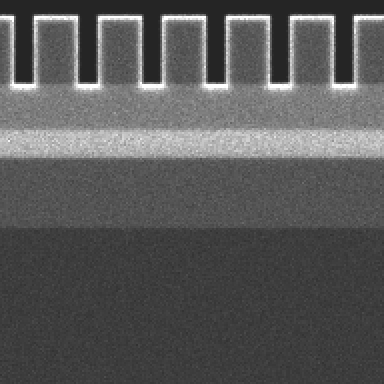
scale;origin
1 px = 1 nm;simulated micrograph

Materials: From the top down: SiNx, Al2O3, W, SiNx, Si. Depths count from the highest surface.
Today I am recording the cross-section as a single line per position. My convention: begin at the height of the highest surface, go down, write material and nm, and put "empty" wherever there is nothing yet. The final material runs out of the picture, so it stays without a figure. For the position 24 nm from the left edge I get empty 68, Al2O3 46, W 28, SiNx 70, Si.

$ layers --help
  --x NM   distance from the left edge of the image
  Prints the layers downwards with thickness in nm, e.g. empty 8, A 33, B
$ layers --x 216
empty 68, Al2O3 46, W 28, SiNx 70, Si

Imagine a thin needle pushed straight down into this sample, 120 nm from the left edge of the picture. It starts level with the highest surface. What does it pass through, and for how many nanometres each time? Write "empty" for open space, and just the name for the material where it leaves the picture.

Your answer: SiNx 68, Al2O3 46, W 28, SiNx 70, Si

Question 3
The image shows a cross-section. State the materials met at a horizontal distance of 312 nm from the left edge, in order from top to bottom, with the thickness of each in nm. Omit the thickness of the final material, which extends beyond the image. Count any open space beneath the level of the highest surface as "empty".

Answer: SiNx 68, Al2O3 46, W 28, SiNx 70, Si